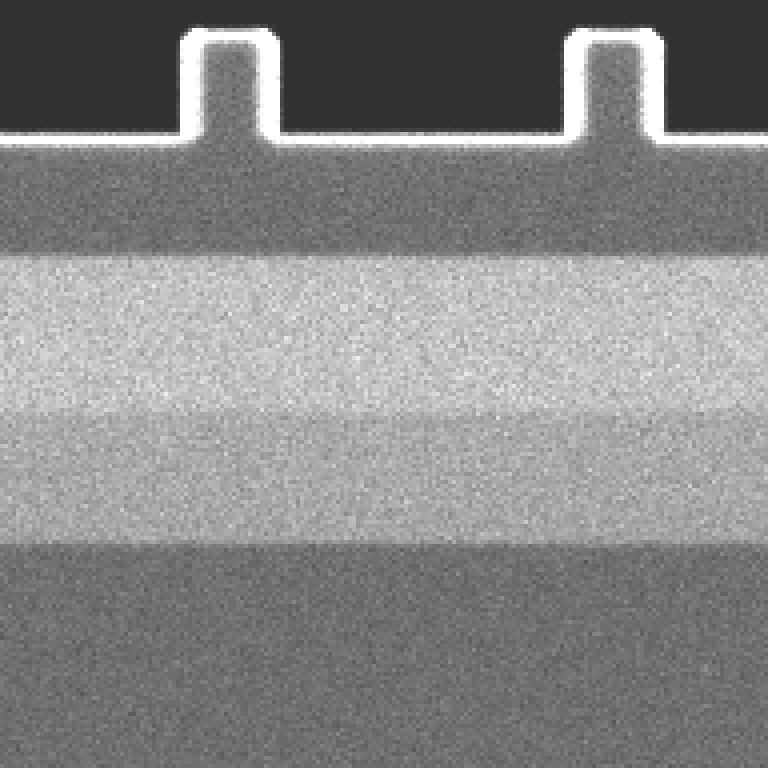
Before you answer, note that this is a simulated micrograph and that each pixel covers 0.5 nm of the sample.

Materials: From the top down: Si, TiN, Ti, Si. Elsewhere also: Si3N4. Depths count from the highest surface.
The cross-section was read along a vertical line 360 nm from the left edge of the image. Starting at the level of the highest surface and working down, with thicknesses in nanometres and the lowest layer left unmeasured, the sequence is empty 52, Si 60, TiN 78, Ti 66, Si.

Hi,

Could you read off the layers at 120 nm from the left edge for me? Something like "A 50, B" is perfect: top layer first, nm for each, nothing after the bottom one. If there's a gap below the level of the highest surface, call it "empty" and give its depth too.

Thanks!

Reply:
Si 112, TiN 78, Ti 66, Si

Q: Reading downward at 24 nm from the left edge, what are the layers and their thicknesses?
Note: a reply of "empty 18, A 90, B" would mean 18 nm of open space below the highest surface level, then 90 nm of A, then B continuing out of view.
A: empty 52, Si 60, TiN 78, Ti 66, Si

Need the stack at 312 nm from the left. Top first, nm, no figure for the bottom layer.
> Si 112, TiN 78, Ti 66, Si